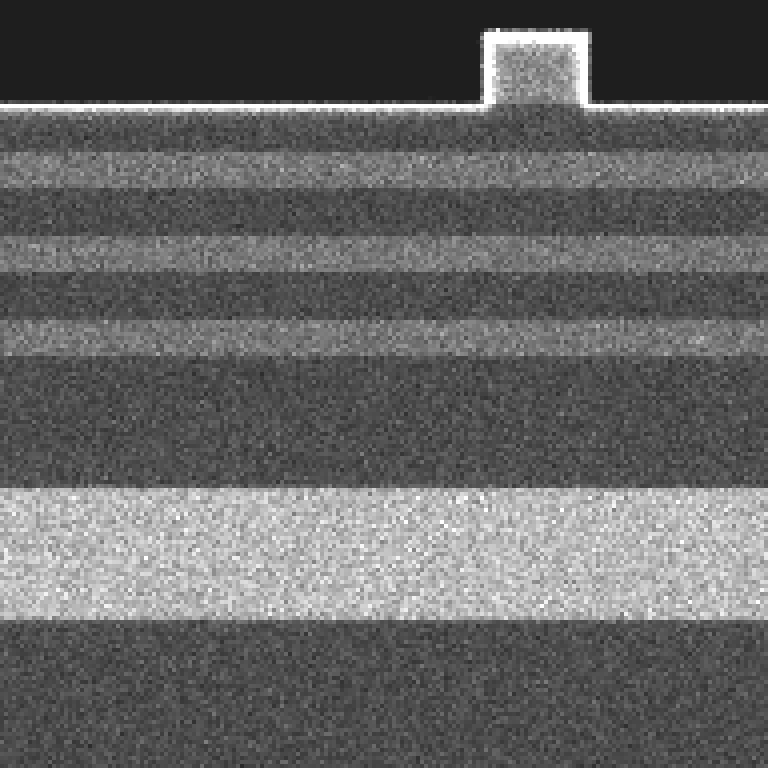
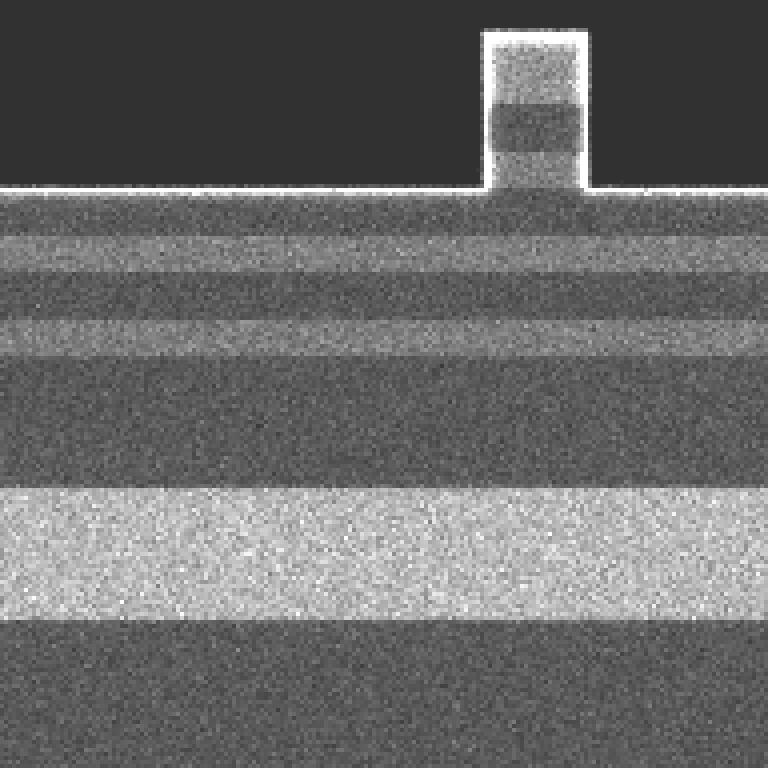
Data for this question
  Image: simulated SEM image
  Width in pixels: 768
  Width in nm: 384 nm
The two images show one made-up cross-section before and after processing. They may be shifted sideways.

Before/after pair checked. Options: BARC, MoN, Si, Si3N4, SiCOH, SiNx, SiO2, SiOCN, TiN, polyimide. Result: removed Si and SiNx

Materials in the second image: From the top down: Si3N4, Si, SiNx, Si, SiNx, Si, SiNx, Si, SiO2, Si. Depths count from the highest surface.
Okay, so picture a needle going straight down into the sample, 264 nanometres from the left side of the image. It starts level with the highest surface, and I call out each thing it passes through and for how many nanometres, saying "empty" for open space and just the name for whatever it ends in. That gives Si3N4 36, Si 24, SiNx 18, Si 24, SiNx 18, Si 24, SiNx 18, Si 66, SiO2 66, Si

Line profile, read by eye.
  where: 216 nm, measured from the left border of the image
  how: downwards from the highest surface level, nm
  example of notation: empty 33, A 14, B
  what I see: empty 78, Si 24, SiNx 18, Si 24, SiNx 18, Si 66, SiO2 66, Si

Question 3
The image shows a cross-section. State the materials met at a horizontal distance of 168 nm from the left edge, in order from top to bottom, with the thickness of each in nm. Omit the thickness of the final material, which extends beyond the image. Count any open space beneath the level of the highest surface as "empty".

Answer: empty 78, Si 24, SiNx 18, Si 24, SiNx 18, Si 66, SiO2 66, Si